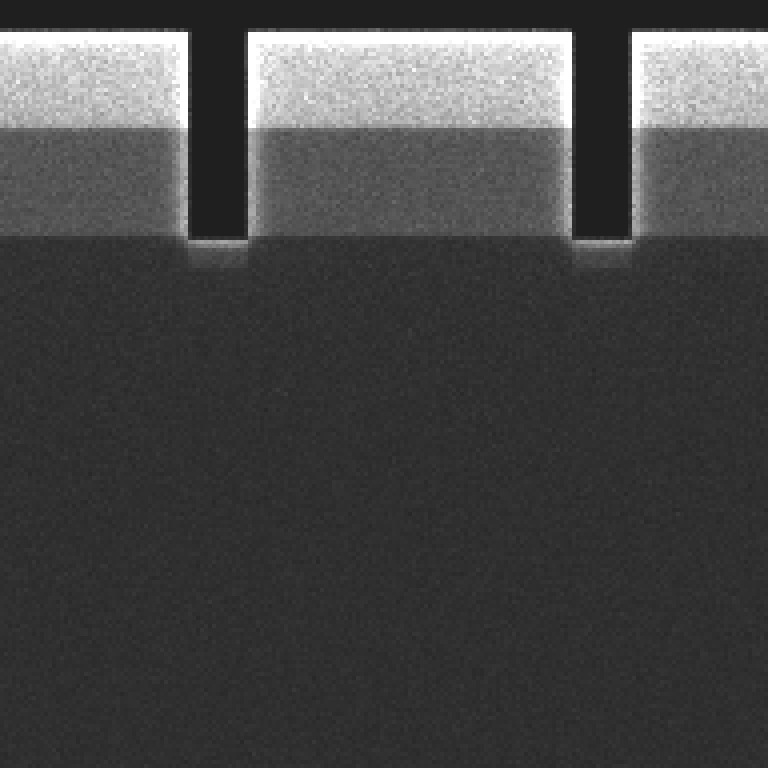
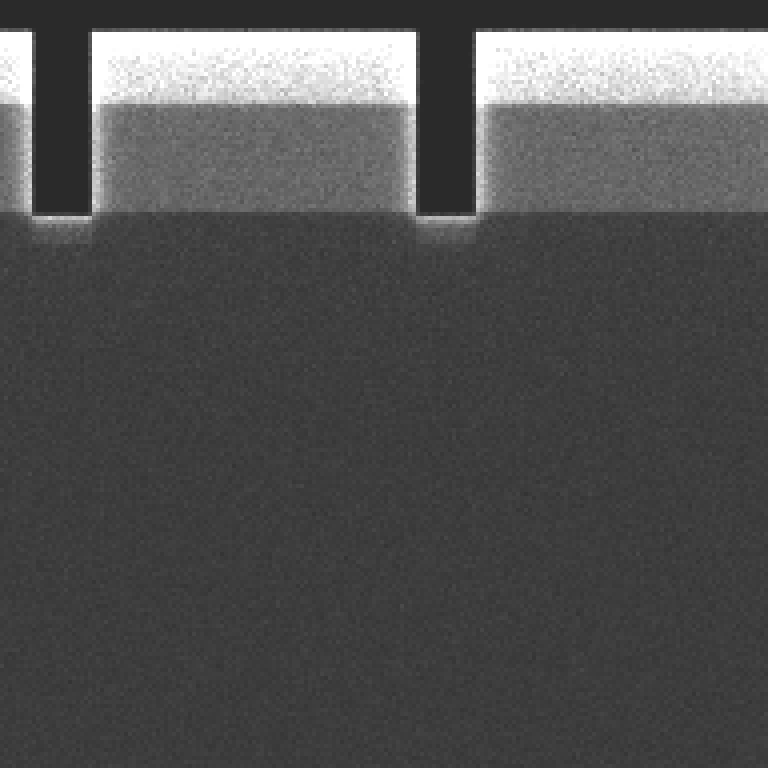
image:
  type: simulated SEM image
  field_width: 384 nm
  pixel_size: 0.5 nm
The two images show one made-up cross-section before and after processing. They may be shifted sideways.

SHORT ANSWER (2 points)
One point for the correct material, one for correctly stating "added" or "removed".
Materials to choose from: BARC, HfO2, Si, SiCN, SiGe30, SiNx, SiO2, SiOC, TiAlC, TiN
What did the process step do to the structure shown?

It removed HfO2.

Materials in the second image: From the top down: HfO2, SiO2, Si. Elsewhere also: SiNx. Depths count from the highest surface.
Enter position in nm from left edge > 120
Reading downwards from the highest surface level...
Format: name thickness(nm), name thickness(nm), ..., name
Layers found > HfO2 36, SiO2 54, Si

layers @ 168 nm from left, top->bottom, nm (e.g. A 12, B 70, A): HfO2 36, SiO2 54, Si